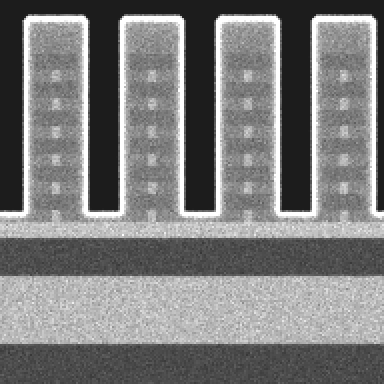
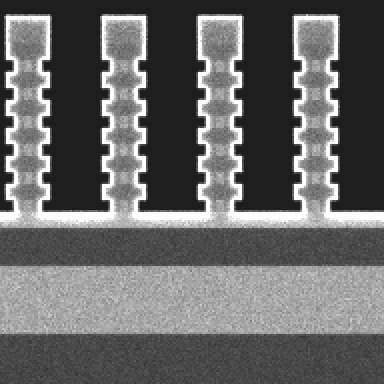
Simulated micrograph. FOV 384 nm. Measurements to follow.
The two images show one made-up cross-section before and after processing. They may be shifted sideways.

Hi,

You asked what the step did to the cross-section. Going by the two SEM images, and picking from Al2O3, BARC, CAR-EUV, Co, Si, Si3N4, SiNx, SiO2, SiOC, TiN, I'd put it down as Si3N4, removed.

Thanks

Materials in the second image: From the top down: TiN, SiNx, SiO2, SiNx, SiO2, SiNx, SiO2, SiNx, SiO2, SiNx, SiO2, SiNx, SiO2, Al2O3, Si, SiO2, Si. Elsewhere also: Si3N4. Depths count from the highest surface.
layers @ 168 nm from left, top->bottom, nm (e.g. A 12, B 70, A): empty 196, Al2O3 16, Si 38, SiO2 68, Si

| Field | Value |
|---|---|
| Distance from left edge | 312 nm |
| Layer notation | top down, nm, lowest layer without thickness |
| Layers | TiN 28, SiNx 16, SiO2 12, SiNx 16, SiO2 12, SiNx 16, SiO2 12, SiNx 16, SiO2 12, SiNx 16, SiO2 12, SiNx 16, SiO2 12, Al2O3 16, Si 38, SiO2 68, Si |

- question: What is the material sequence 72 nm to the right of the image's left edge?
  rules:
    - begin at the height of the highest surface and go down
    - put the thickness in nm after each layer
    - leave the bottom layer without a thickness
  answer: empty 196, Al2O3 16, Si 38, SiO2 68, Si